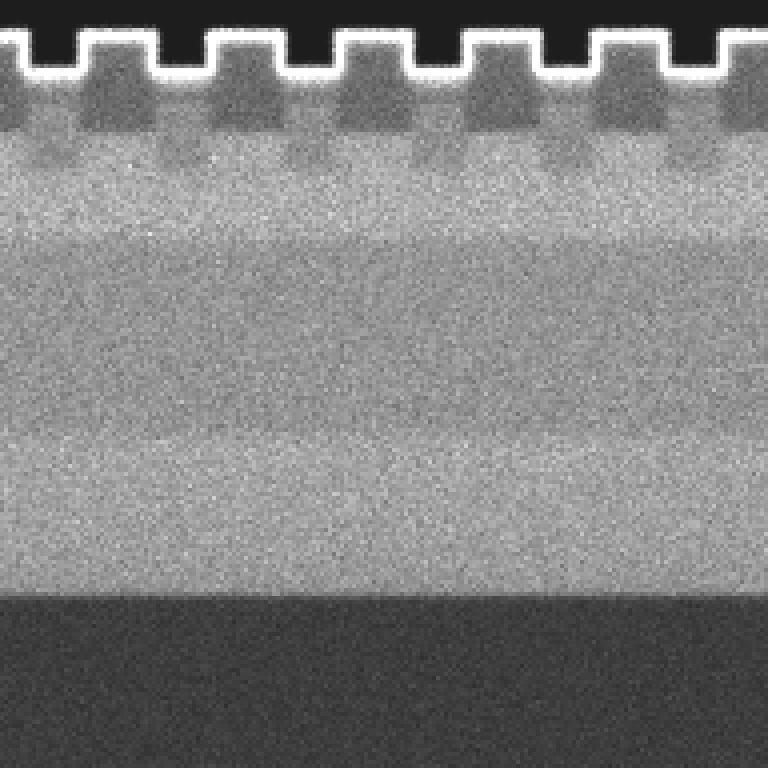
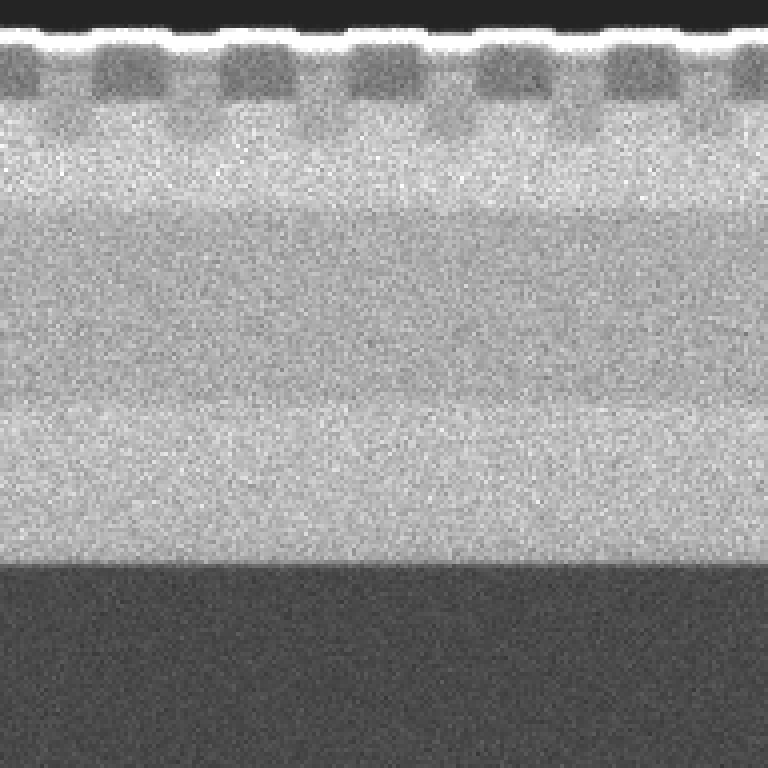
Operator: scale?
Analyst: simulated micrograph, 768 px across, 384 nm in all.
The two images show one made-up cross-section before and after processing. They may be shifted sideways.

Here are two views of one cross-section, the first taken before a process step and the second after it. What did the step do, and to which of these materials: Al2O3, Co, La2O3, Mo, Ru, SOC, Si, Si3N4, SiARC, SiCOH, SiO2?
It removed Si3N4.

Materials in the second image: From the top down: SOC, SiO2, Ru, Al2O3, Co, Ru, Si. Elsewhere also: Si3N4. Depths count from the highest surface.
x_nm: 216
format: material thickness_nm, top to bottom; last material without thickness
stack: empty 2, SOC 18, SiO2 34, Ru 34, Al2O3 58, Co 40, Ru 80, Si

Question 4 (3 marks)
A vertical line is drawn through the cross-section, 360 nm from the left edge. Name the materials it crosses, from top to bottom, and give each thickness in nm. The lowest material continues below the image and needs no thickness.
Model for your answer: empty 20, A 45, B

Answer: empty 2, SOC 18, SiO2 34, Ru 34, Al2O3 58, Co 40, Ru 80, Si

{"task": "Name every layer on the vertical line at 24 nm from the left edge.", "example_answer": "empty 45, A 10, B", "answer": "empty 2, SOC 18, SiO2 34, Ru 34, Al2O3 58, Co 40, Ru 80, Si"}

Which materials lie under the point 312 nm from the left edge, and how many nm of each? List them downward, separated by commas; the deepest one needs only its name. Si3N4 34, Ru 54, Al2O3 58, Co 40, Ru 80, Si